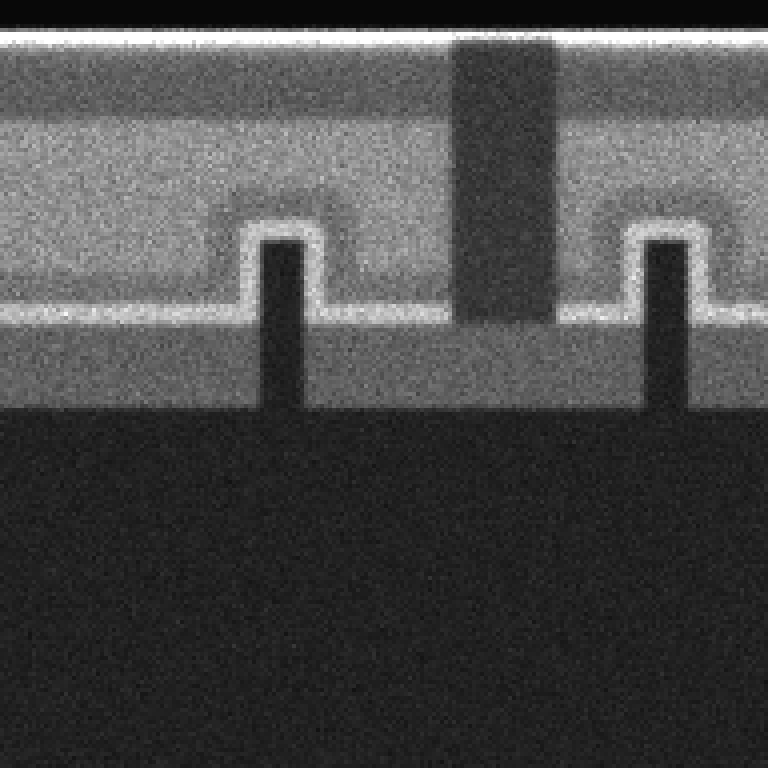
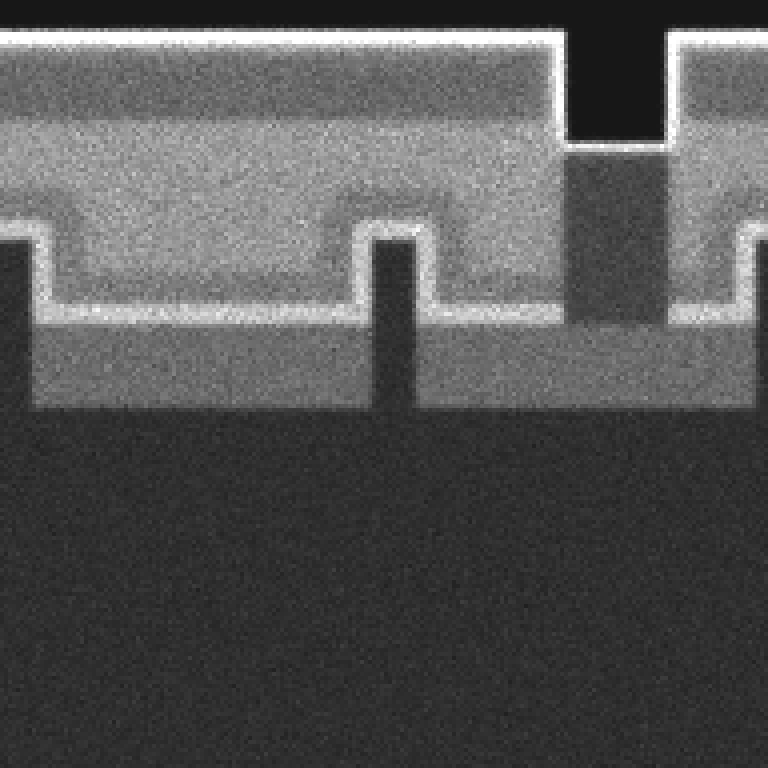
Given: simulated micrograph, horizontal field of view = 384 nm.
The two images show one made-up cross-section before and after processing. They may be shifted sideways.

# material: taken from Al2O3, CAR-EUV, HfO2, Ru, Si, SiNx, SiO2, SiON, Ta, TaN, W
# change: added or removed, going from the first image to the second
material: SiNx
change: removed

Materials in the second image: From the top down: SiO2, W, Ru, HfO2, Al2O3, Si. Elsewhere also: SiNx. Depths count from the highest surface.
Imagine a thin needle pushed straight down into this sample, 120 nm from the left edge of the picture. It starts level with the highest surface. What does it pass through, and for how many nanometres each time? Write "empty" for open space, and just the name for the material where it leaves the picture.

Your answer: SiO2 44, W 76, Ru 16, HfO2 10, Al2O3 42, Si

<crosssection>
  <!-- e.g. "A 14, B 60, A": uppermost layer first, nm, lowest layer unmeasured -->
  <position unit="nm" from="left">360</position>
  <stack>SiO2 44, W 38, Ru 54, HfO2 10, Al2O3 42, Si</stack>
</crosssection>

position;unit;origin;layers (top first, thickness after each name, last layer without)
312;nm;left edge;empty 56, SiNx 90, Al2O3 42, Si